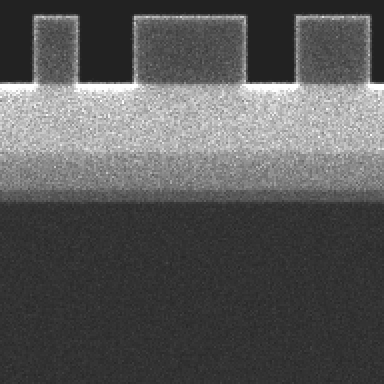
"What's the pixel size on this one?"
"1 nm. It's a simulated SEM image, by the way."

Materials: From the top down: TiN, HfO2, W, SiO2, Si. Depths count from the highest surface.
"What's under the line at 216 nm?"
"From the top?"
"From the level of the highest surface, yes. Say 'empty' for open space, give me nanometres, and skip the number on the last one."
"TiN 68, HfO2 68, W 38, SiO2 12, Si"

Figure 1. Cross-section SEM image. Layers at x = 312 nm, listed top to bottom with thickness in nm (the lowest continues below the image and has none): TiN 68, HfO2 68, W 38, SiO2 12, Si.